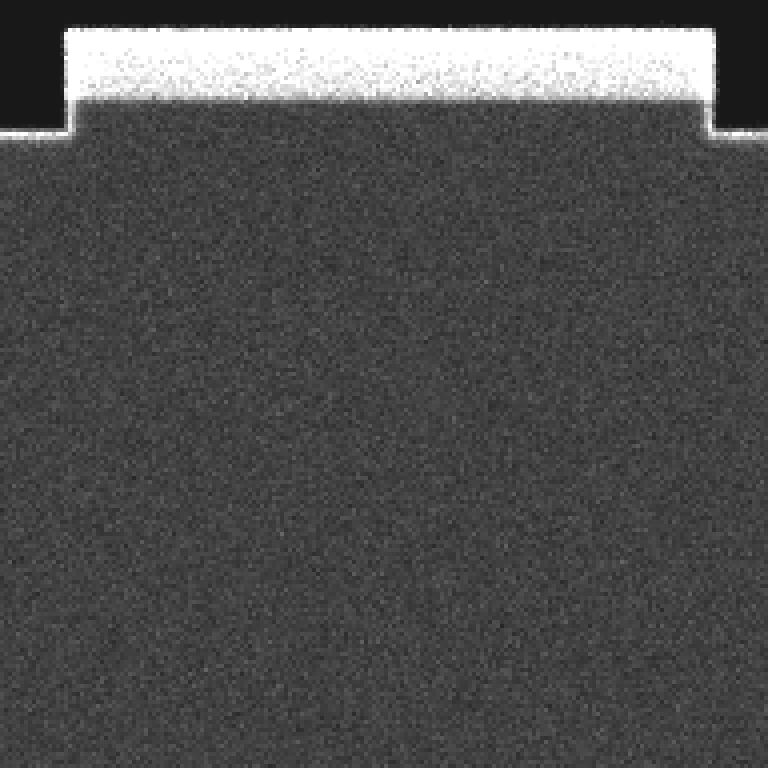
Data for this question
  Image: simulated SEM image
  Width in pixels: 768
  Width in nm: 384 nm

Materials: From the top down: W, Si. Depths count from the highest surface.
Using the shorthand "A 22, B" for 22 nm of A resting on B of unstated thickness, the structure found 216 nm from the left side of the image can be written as W 34, Si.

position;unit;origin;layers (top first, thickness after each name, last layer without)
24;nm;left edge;empty 50, Si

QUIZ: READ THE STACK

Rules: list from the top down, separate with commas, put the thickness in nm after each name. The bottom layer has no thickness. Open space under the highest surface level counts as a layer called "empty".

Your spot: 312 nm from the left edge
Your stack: W 34, Si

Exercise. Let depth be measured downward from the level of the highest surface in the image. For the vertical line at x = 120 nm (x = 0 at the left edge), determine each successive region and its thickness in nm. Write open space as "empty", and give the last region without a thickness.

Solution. W 34, Si